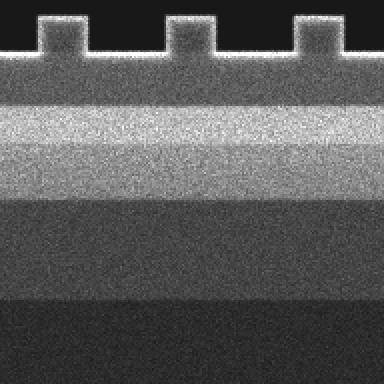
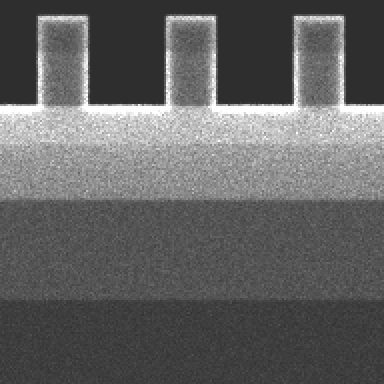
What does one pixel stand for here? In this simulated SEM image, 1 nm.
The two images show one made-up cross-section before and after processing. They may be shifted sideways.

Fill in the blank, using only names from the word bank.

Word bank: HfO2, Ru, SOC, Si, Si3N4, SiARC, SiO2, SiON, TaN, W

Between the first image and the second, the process removed SiO2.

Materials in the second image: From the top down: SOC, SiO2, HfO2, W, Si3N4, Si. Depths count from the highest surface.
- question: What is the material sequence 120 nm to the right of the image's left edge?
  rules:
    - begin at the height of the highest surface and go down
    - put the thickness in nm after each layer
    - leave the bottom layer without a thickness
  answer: empty 90, HfO2 38, W 56, Si3N4 100, Si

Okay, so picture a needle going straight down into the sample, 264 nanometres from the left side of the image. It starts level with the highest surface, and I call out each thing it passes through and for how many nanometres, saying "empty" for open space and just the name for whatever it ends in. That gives empty 90, HfO2 38, W 56, Si3N4 100, Si